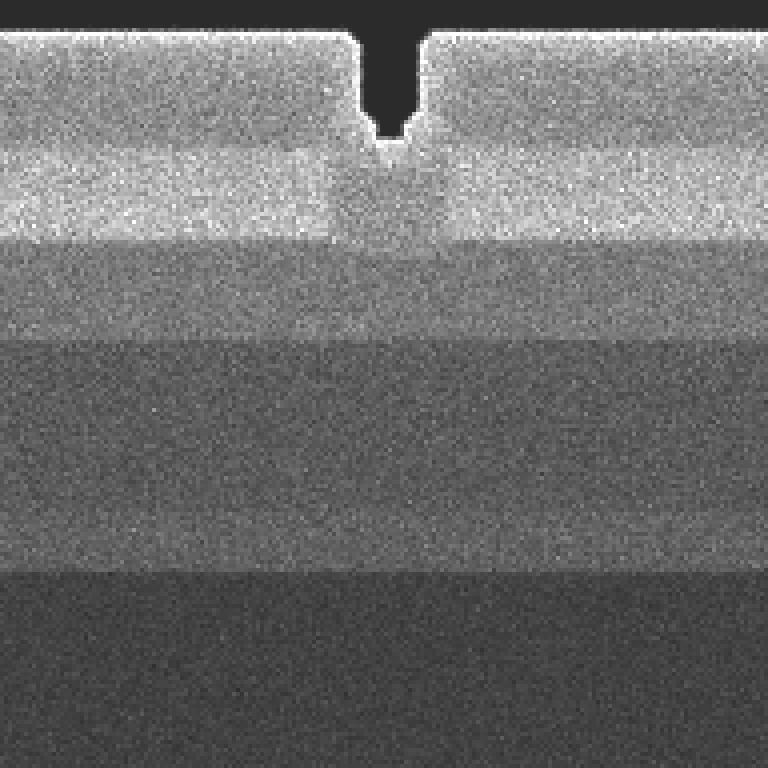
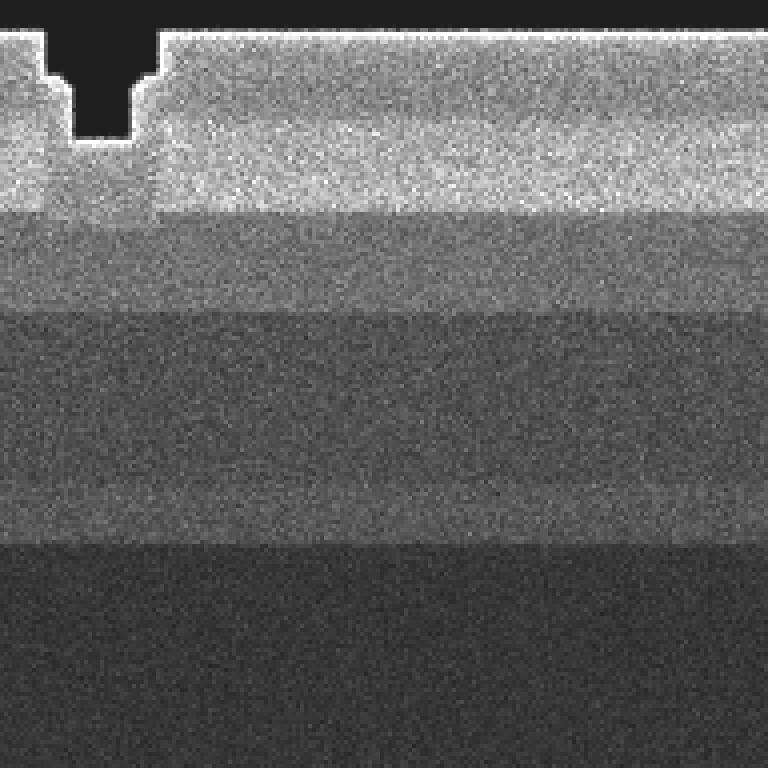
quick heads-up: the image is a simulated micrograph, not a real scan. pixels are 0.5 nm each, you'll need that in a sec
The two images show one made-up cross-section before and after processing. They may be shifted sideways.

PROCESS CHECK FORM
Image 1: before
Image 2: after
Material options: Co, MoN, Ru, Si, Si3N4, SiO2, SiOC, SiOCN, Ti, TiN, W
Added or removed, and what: removed, Ru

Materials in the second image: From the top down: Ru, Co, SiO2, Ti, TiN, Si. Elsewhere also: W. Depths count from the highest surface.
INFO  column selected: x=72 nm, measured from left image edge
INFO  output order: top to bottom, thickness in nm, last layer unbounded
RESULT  empty 22, Ru 18, Co 58, SiO2 42, Ti 86, TiN 30, Si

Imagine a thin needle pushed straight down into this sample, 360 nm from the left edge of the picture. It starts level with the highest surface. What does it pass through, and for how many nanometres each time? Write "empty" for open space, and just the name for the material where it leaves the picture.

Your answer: Co 44, W 46, SiO2 50, Ti 86, TiN 30, Si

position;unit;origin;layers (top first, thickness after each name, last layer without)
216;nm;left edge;Co 44, W 46, SiO2 50, Ti 86, TiN 30, Si